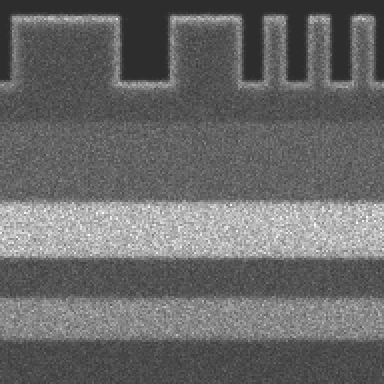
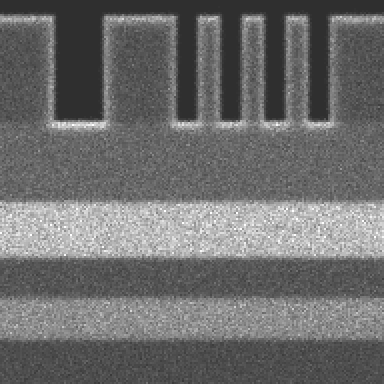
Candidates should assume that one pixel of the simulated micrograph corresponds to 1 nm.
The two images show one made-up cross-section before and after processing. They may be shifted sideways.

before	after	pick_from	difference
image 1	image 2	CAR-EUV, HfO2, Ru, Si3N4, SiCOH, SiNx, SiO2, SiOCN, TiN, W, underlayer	underlayer removed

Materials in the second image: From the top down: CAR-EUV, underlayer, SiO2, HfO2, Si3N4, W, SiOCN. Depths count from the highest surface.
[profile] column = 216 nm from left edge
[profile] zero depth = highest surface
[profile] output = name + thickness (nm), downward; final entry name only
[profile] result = CAR-EUV 66, underlayer 40, SiO2 80, HfO2 56, Si3N4 40, W 42, SiOCN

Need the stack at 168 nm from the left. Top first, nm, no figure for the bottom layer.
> CAR-EUV 66, underlayer 40, SiO2 80, HfO2 56, Si3N4 40, W 42, SiOCN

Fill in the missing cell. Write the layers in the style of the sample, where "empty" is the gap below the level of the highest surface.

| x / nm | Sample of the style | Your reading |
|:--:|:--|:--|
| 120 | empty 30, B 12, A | CAR-EUV 66, underlayer 40, SiO2 80, HfO2 56, Si3N4 40, W 42, SiOCN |